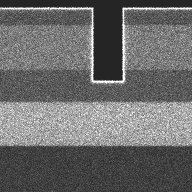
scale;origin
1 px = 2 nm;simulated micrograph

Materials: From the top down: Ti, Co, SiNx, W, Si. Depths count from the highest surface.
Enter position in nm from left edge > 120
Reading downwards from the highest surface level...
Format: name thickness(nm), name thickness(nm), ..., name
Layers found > Ti 34, Co 90, SiNx 64, W 88, Si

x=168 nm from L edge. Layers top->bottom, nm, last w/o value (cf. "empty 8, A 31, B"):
Ti 34, Co 90, SiNx 64, W 88, Si